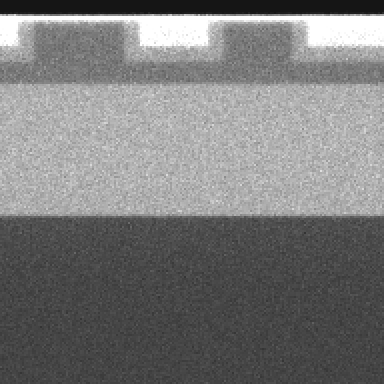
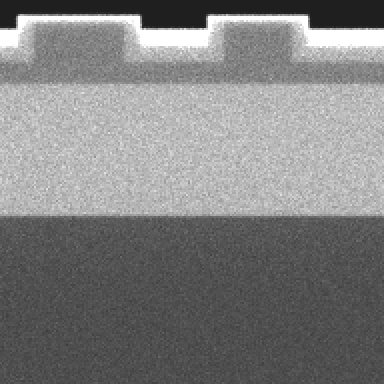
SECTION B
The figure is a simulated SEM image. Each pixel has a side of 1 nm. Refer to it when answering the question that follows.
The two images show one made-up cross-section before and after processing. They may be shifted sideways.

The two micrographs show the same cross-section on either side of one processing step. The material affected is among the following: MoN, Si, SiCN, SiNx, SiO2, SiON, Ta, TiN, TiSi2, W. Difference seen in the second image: W removed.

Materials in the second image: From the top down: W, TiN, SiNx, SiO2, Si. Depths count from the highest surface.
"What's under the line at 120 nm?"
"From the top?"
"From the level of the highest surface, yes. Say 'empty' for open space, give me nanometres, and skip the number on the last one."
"SiNx 68, SiO2 132, Si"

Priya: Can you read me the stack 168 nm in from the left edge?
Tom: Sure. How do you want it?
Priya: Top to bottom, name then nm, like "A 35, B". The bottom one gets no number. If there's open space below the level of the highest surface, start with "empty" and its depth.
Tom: empty 14, W 16, TiN 16, SiNx 22, SiO2 132, Si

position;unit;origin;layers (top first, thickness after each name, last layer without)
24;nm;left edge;TiN 46, SiNx 22, SiO2 132, Si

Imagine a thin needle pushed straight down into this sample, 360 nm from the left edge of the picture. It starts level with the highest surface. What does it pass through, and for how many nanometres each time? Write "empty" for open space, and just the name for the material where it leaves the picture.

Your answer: empty 14, W 16, TiN 16, SiNx 22, SiO2 132, Si